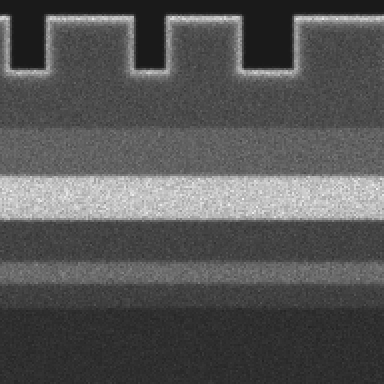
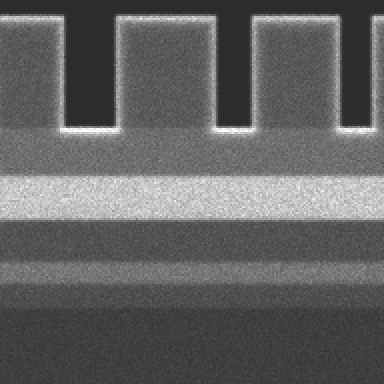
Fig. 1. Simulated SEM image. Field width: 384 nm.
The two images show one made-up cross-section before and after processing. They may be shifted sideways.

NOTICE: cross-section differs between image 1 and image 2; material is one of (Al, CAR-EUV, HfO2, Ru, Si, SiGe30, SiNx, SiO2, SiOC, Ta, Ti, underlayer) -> removed: underlayer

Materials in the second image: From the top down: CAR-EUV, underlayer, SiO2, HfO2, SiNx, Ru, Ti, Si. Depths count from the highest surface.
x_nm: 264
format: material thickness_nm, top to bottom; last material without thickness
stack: CAR-EUV 54, underlayer 58, SiO2 48, HfO2 44, SiNx 42, Ru 22, Ti 24, Si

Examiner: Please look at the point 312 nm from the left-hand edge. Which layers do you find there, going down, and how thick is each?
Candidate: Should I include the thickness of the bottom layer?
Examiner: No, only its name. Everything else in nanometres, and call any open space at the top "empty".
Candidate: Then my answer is CAR-EUV 54, underlayer 58, SiO2 48, HfO2 44, SiNx 42, Ru 22, Ti 24, Si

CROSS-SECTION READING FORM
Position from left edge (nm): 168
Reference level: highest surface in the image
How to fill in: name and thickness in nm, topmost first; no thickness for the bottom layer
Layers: CAR-EUV 54, underlayer 58, SiO2 48, HfO2 44, SiNx 42, Ru 22, Ti 24, Si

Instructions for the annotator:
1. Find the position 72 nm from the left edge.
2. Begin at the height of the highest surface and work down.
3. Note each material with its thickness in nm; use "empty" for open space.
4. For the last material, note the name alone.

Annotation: empty 112, SiO2 48, HfO2 44, SiNx 42, Ru 22, Ti 24, Si